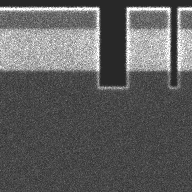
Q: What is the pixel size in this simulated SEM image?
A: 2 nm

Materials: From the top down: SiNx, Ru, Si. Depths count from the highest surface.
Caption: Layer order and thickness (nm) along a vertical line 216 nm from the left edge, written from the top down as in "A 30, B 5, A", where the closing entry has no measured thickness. empty 158, Si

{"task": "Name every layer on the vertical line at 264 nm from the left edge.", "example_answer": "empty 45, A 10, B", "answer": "SiNx 42, Ru 84, Si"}